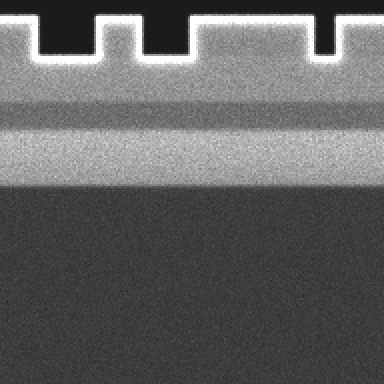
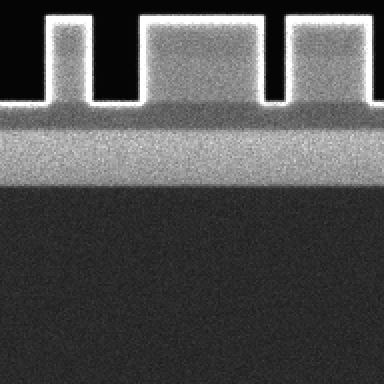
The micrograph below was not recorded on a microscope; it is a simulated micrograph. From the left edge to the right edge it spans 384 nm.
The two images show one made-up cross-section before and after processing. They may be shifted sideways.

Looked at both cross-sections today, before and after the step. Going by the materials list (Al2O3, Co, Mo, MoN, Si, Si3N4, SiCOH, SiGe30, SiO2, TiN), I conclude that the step removed Al2O3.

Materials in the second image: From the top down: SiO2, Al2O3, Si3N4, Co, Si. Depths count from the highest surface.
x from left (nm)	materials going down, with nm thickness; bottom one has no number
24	empty 86, Si3N4 28, Co 56, Si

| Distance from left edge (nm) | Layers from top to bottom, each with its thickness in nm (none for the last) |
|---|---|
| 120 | empty 86, Si3N4 28, Co 56, Si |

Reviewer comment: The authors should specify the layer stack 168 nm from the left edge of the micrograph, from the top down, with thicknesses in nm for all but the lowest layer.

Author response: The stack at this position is SiO2 40, Al2O3 46, Si3N4 28, Co 56, Si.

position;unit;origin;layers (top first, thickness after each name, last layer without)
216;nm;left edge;SiO2 40, Al2O3 46, Si3N4 28, Co 56, Si